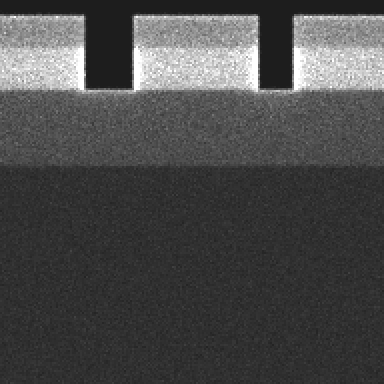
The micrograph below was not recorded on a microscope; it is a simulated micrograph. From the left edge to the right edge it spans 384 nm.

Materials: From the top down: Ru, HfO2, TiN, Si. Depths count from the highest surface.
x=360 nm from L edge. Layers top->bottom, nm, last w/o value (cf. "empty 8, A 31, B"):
Ru 32, HfO2 42, TiN 76, Si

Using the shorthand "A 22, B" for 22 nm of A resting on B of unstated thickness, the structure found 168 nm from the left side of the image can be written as Ru 32, HfO2 42, TiN 76, Si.